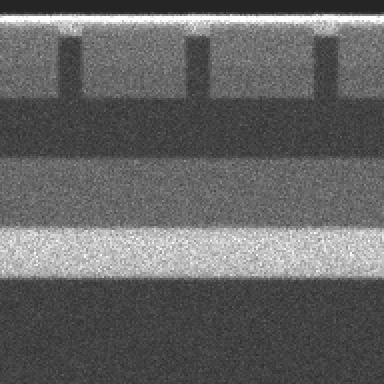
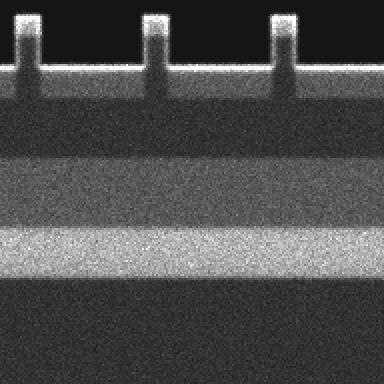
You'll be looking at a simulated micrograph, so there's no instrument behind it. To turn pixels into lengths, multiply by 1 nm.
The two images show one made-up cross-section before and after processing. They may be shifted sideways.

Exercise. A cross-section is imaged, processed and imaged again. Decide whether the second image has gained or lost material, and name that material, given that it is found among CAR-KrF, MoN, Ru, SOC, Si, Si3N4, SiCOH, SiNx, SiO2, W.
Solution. removed: SOC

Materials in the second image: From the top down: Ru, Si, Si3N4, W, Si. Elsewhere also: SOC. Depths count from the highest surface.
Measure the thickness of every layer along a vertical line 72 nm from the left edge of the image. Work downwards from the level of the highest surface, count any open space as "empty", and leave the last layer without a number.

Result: empty 50, Si3N4 32, Si 60, Si3N4 70, W 50, Si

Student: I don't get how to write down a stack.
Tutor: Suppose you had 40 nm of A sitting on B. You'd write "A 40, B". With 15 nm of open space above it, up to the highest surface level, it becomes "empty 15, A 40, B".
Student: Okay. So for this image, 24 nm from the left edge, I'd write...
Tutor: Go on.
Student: Ru 20, Si 122, Si3N4 70, W 50, Si